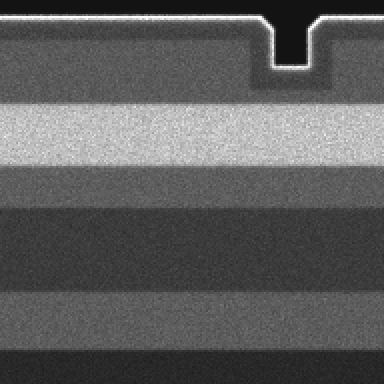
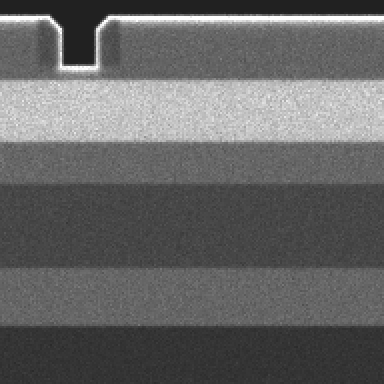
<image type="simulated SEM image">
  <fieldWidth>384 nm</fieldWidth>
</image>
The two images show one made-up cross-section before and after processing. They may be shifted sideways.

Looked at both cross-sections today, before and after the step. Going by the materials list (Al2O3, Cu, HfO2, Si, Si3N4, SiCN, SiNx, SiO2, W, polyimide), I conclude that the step removed Si3N4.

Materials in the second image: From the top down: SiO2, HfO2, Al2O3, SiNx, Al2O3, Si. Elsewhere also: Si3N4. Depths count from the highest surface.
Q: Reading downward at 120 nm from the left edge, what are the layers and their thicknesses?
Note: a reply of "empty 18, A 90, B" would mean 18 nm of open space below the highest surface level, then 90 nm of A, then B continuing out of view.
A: SiO2 64, HfO2 62, Al2O3 42, SiNx 84, Al2O3 58, Si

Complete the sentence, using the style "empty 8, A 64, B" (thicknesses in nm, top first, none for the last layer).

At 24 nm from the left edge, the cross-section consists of SiO2 64, HfO2 62, Al2O3 42, SiNx 84, Al2O3 58, Si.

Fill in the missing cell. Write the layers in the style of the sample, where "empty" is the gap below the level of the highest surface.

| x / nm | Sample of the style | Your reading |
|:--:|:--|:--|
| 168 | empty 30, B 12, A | SiO2 64, HfO2 62, Al2O3 42, SiNx 84, Al2O3 58, Si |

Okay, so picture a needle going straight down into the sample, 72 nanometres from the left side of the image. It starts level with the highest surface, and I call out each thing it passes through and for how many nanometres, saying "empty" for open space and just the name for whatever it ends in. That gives empty 50, SiO2 14, HfO2 62, Al2O3 42, SiNx 84, Al2O3 58, Si